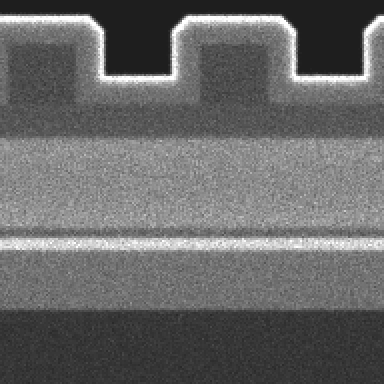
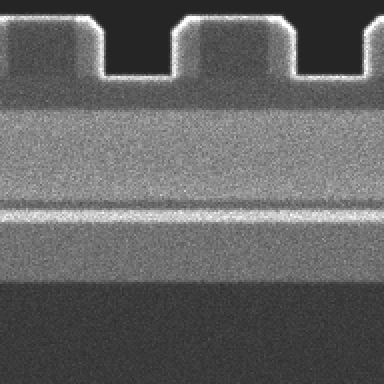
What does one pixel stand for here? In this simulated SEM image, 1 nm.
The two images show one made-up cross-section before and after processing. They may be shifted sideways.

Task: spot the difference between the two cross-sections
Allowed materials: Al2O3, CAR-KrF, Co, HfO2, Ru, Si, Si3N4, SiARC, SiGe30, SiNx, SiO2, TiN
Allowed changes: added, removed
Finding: removed SiO2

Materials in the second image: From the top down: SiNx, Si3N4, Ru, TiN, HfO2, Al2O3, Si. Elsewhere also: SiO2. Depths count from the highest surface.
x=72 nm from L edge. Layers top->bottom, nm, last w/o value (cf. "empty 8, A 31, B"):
SiNx 60, Si3N4 34, Ru 90, TiN 10, HfO2 12, Al2O3 60, Si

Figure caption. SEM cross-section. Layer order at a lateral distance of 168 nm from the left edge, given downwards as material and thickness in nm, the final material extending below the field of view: empty 60, Si3N4 34, Ru 90, TiN 10, HfO2 12, Al2O3 60, Si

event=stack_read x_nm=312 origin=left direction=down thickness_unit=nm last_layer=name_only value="empty 60, Si3N4 34, Ru 90, TiN 10, HfO2 12, Al2O3 60, Si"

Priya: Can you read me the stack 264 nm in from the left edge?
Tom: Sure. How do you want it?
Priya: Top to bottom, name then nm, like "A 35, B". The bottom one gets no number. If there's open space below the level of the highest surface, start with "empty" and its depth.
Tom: SiNx 60, Si3N4 34, Ru 90, TiN 10, HfO2 12, Al2O3 60, Si